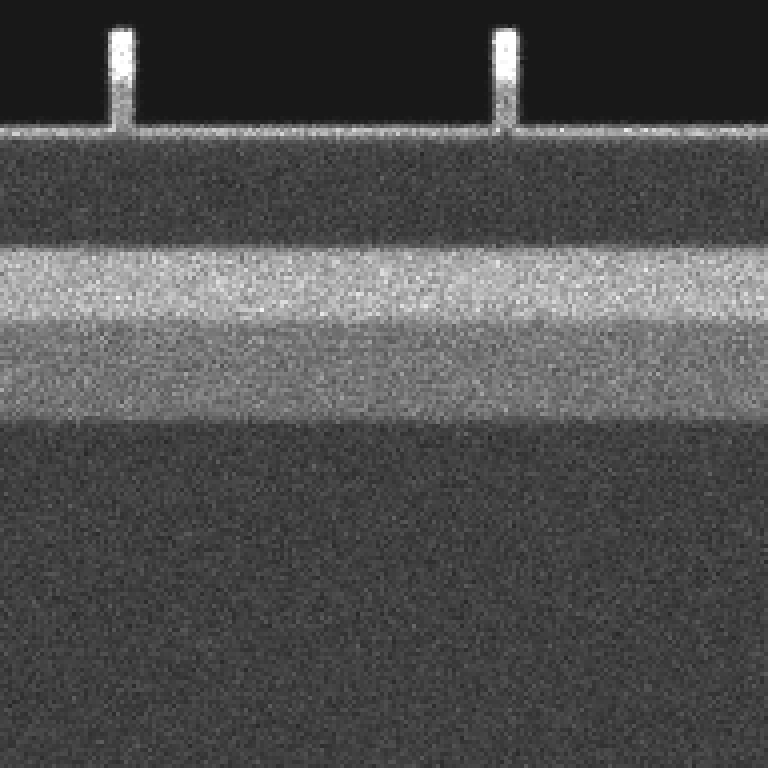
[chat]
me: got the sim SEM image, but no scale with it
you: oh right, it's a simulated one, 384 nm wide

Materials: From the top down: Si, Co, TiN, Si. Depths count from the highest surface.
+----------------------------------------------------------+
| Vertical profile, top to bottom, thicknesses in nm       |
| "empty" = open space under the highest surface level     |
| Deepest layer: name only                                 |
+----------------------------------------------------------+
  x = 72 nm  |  empty 48, Si 60, Co 36, TiN 50, Si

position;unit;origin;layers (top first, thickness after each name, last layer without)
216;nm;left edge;empty 48, Si 60, Co 36, TiN 50, Si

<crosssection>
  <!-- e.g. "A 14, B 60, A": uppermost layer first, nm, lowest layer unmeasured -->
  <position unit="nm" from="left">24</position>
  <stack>empty 48, Si 60, Co 36, TiN 50, Si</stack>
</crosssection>